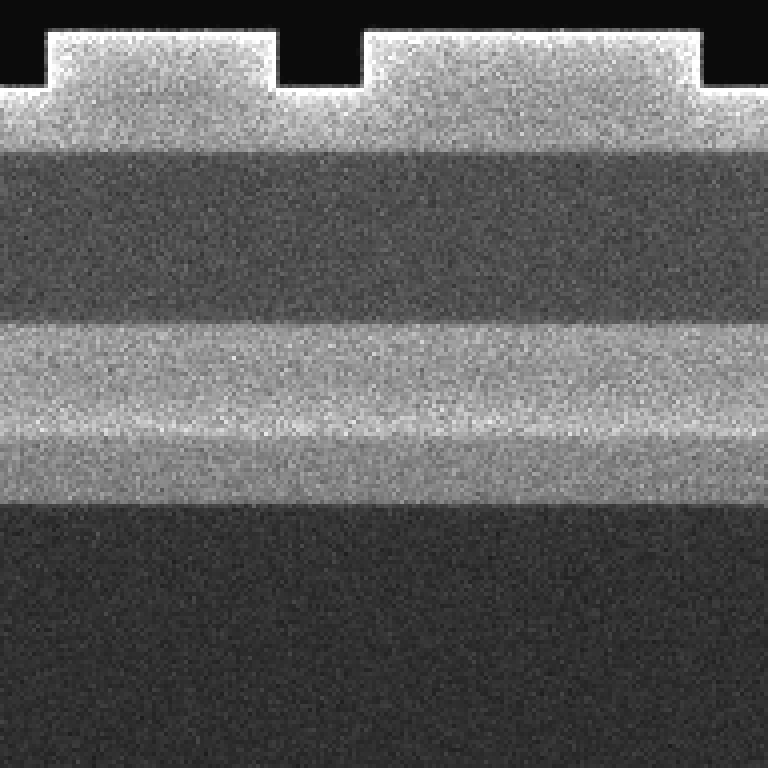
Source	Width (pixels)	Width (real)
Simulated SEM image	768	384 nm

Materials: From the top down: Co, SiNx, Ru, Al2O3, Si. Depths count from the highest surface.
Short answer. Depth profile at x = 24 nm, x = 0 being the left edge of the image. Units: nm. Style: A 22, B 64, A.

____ Co 60, SiNx 86, Ru 56, Al2O3 34, Si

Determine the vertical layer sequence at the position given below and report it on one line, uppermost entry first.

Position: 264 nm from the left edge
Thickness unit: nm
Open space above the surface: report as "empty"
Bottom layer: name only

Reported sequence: Co 60, SiNx 86, Ru 56, Al2O3 34, Si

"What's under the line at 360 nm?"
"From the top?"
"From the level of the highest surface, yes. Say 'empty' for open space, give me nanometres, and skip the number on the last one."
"empty 28, Co 32, SiNx 86, Ru 56, Al2O3 34, Si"